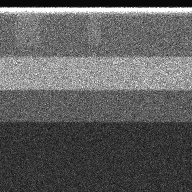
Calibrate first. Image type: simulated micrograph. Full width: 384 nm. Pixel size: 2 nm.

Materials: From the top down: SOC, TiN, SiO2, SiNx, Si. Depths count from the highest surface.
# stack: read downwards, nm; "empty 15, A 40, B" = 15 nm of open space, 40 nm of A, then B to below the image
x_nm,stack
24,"SOC 10, TiN 88, SiO2 66, SiNx 64, Si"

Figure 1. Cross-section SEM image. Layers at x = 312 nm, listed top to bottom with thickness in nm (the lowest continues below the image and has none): SOC 10, TiN 88, SiO2 66, SiNx 64, Si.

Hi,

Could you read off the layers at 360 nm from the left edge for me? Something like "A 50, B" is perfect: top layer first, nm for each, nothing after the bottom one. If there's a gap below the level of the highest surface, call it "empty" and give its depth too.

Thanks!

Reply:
SOC 10, TiN 88, SiO2 66, SiNx 64, Si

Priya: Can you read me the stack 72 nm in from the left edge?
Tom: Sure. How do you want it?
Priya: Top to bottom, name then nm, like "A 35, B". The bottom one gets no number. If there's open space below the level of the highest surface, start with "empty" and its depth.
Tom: SOC 74, TiN 24, SiO2 66, SiNx 64, Si